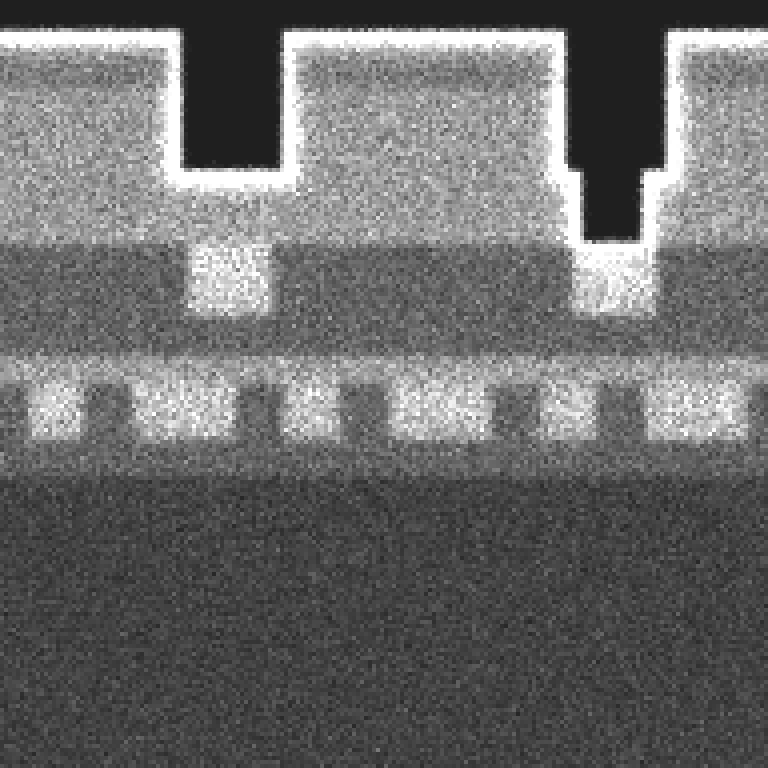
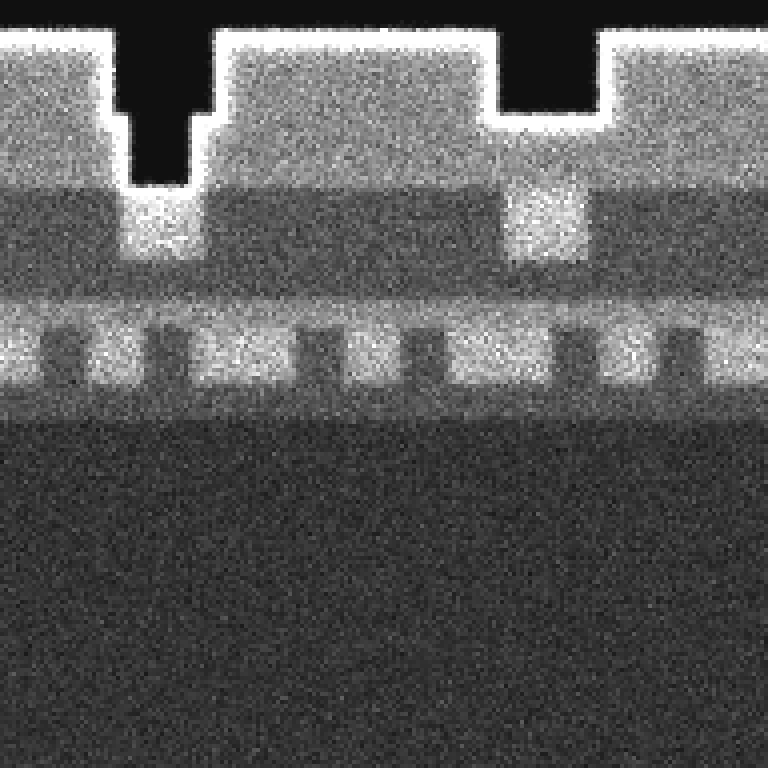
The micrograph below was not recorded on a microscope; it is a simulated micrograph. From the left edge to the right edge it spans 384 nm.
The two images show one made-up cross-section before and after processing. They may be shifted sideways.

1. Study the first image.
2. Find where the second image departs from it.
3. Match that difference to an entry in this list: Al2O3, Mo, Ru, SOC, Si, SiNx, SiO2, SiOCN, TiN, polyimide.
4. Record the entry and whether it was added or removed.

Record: SOC / removed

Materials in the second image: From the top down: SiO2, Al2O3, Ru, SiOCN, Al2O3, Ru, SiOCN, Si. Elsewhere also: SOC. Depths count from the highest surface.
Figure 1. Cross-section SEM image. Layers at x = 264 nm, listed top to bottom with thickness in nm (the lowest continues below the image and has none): empty 42, SiO2 24, Al2O3 12, Ru 36, SiOCN 20, Al2O3 14, Ru 28, SiOCN 18, Si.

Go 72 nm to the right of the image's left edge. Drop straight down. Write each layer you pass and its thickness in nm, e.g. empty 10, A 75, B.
empty 78, Ru 36, SiOCN 20, Al2O3 14, SiOCN 46, Si